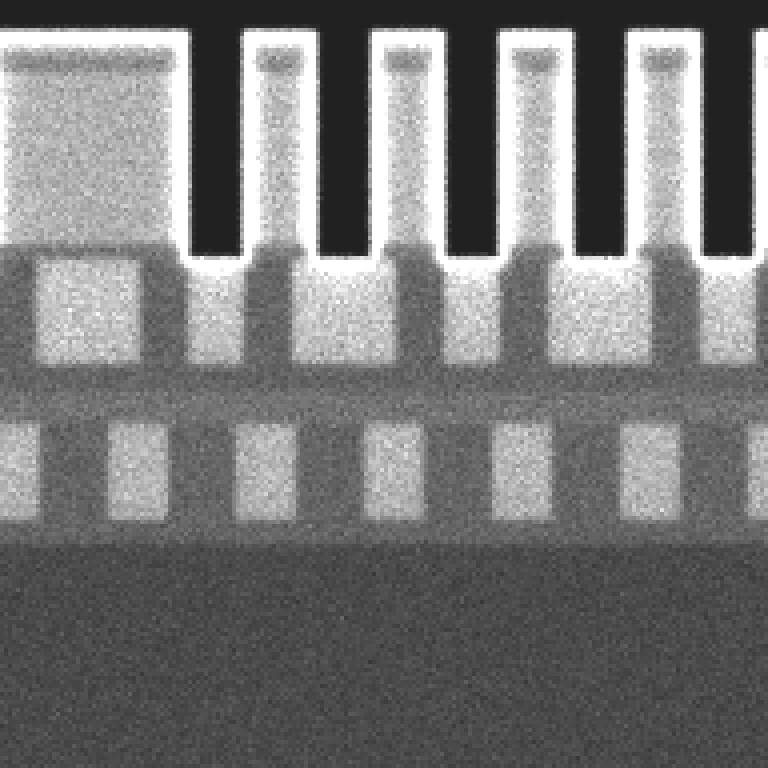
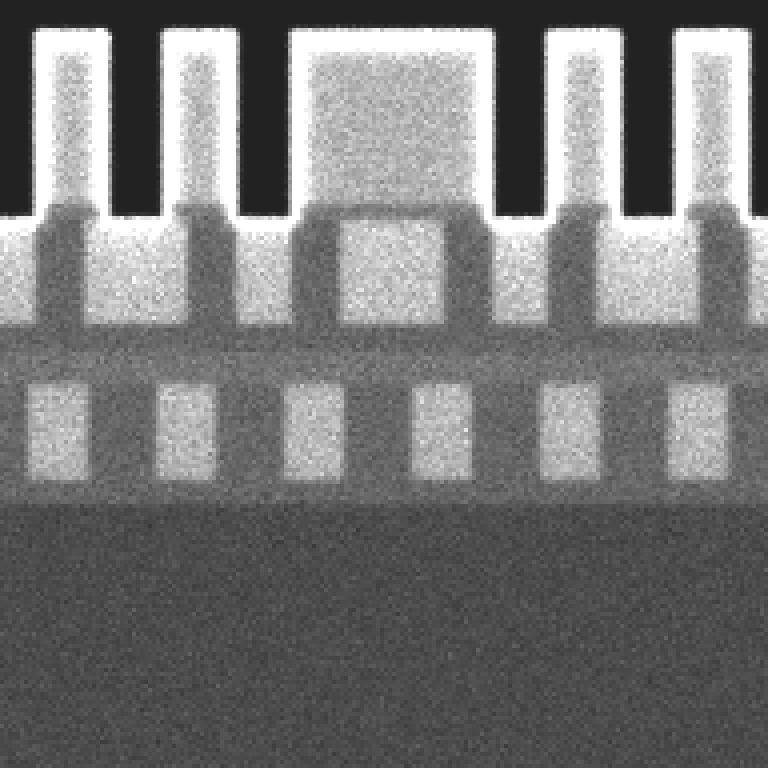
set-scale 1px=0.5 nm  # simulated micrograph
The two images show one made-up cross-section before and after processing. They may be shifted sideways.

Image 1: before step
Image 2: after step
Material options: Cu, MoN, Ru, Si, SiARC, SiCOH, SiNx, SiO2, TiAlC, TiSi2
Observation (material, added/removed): SiARC, removed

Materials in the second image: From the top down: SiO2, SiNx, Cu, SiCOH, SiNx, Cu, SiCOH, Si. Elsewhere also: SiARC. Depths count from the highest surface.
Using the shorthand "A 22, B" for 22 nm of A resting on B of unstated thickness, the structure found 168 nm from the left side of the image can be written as SiO2 86, SiNx 8, SiCOH 66, SiNx 16, Cu 48, SiCOH 12, Si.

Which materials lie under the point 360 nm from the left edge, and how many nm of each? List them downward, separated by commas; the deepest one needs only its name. SiO2 86, SiNx 8, SiCOH 66, SiNx 16, Cu 48, SiCOH 12, Si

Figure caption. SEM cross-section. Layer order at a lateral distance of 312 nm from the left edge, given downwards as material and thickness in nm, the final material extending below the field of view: empty 94, Cu 52, SiCOH 14, SiNx 16, SiCOH 60, Si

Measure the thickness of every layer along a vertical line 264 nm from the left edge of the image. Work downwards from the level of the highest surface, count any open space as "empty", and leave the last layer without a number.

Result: empty 94, Cu 52, SiCOH 14, SiNx 16, SiCOH 60, Si